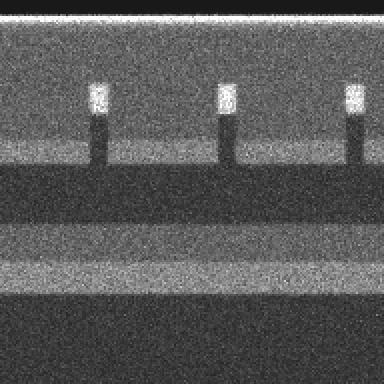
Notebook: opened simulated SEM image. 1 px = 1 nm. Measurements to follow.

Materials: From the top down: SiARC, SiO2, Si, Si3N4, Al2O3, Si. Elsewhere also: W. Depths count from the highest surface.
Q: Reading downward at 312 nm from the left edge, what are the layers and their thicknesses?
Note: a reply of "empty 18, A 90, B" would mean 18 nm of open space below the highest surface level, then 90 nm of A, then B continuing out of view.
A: SiARC 124, SiO2 24, Si 60, Si3N4 38, Al2O3 32, Si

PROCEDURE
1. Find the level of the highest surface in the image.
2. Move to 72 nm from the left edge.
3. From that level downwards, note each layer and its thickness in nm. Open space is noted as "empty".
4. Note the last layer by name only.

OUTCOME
SiARC 124, SiO2 24, Si 60, Si3N4 38, Al2O3 32, Si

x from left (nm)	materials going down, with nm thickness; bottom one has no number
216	SiARC 124, SiO2 24, Si 60, Si3N4 38, Al2O3 32, Si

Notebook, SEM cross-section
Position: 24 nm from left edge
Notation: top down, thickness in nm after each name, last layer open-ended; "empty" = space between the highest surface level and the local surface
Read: SiARC 124, SiO2 24, Si 60, Si3N4 38, Al2O3 32, Si